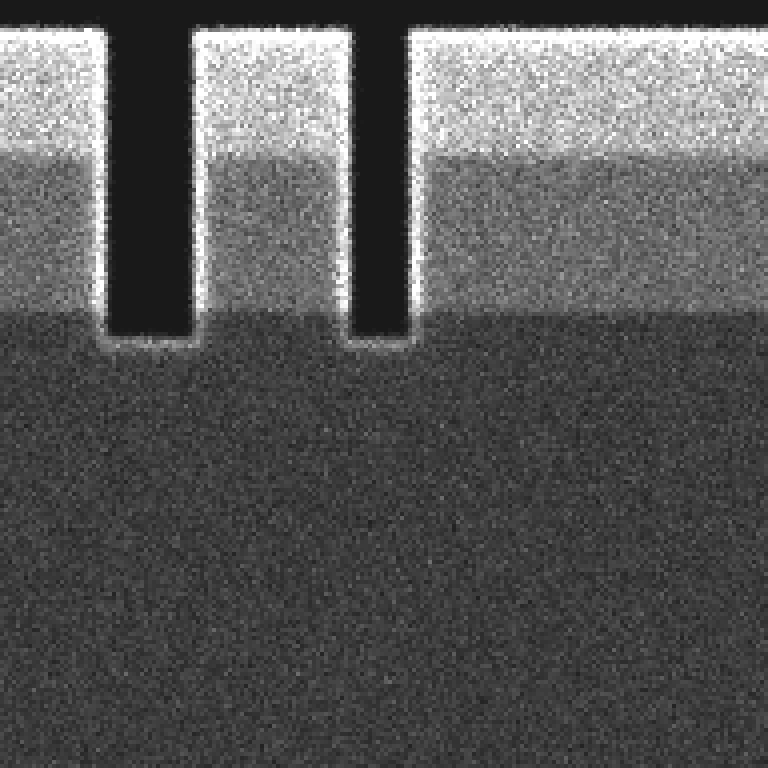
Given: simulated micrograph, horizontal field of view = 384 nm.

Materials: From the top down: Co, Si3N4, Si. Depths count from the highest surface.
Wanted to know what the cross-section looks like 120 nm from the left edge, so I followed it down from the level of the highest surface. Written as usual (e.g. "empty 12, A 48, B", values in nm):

Co 62, Si3N4 78, Si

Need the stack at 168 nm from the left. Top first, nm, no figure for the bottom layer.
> Co 62, Si3N4 78, Si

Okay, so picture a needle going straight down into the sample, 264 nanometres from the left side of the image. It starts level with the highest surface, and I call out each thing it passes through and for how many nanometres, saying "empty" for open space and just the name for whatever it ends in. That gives Co 62, Si3N4 78, Si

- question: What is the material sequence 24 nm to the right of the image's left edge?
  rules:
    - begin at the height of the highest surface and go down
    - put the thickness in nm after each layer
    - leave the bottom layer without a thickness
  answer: Co 62, Si3N4 78, Si